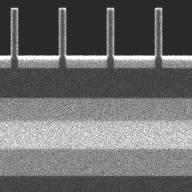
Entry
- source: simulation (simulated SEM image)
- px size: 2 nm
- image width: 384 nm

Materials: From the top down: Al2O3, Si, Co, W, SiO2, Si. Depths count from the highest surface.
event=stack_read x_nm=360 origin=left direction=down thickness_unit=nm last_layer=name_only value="empty 96, Al2O3 24, Si 60, Co 46, W 56, SiO2 54, Si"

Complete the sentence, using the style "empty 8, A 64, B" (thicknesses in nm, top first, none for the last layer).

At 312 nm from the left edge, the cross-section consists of Si 180, Co 46, W 56, SiO2 54, Si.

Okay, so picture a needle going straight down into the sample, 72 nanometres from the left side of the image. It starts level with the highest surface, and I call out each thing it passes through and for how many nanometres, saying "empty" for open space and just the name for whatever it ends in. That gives empty 96, Al2O3 24, Si 60, Co 46, W 56, SiO2 54, Si